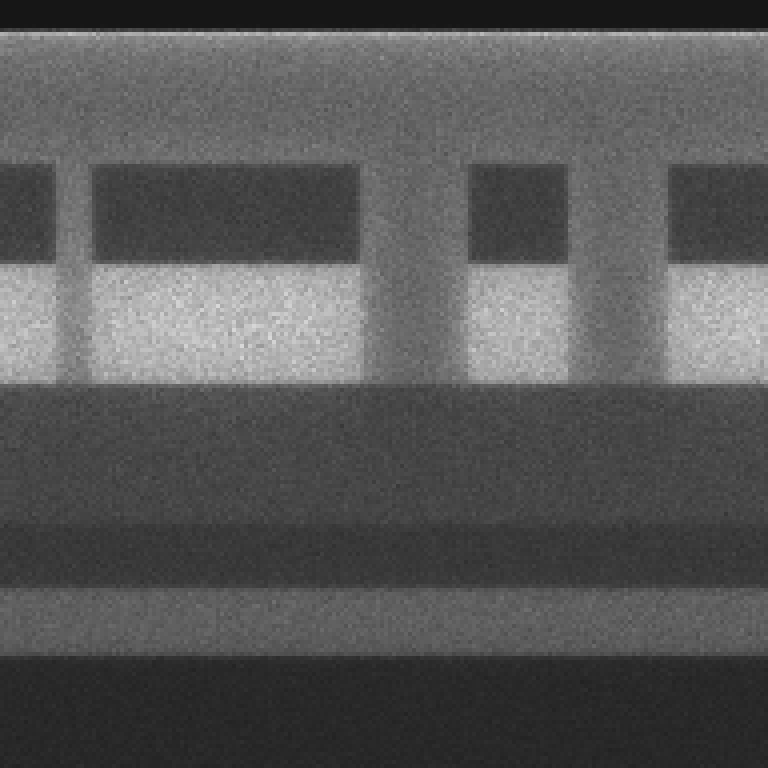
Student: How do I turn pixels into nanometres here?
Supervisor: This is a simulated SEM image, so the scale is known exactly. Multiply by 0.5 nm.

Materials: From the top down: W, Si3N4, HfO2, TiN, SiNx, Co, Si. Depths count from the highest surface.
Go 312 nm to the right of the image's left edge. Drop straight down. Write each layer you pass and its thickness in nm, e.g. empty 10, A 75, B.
W 176, TiN 70, SiNx 32, Co 34, Si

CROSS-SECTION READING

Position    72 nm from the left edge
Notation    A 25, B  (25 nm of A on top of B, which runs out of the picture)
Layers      W 66, Si3N4 50, HfO2 60, TiN 70, SiNx 32, Co 34, Si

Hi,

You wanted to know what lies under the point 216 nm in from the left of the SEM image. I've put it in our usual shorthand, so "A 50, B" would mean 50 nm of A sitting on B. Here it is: W 176, TiN 70, SiNx 32, Co 34, Si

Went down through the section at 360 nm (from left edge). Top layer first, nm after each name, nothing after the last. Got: W 66, Si3N4 50, HfO2 60, TiN 70, SiNx 32, Co 34, Si